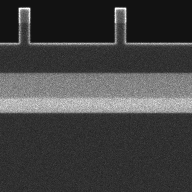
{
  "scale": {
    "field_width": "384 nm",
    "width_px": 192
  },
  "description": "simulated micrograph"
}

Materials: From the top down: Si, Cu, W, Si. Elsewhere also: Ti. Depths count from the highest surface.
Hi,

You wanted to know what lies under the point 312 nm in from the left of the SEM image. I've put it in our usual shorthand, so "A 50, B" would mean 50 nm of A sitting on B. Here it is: empty 70, Si 60, Cu 50, W 30, Si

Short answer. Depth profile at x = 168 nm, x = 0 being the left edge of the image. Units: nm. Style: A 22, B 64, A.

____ empty 70, Si 60, Cu 50, W 30, Si